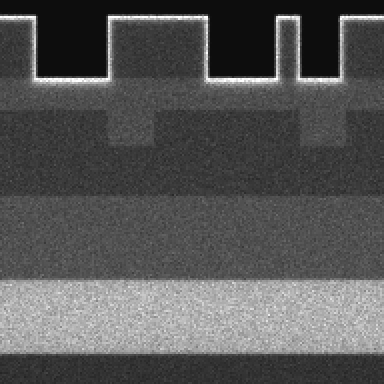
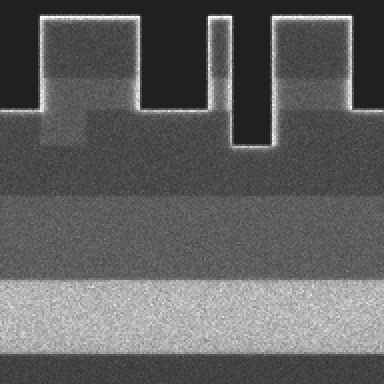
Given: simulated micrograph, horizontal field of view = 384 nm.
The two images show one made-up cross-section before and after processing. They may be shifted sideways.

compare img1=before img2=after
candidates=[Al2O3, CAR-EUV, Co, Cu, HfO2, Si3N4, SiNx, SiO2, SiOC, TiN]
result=removed:SiO2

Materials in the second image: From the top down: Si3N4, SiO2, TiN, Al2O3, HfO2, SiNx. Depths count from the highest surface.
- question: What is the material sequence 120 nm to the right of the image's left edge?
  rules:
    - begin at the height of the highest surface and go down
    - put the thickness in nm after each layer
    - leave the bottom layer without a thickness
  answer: Si3N4 62, SiO2 32, TiN 86, Al2O3 84, HfO2 74, SiNx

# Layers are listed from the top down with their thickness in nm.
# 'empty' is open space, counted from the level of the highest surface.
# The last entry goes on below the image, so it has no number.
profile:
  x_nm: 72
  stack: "Si3N4 62, SiO2 68, TiN 50, Al2O3 84, HfO2 74, SiNx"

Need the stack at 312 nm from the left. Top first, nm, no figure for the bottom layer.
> Si3N4 62, SiO2 32, TiN 86, Al2O3 84, HfO2 74, SiNx